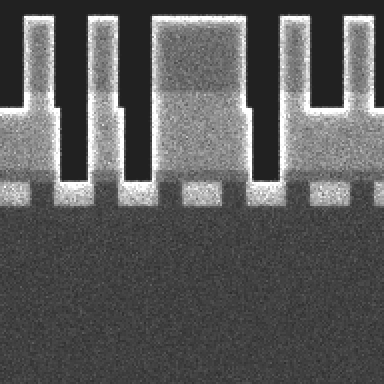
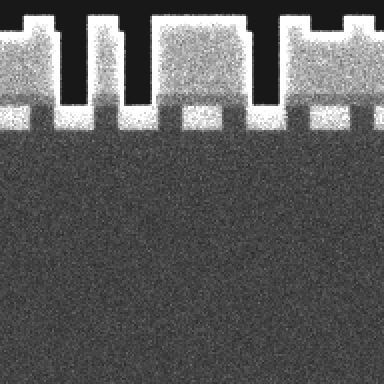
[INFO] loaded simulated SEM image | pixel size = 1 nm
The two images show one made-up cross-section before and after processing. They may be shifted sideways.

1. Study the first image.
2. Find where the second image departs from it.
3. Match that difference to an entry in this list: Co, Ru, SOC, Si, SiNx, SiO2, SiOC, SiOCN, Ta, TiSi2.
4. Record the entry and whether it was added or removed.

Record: SOC / removed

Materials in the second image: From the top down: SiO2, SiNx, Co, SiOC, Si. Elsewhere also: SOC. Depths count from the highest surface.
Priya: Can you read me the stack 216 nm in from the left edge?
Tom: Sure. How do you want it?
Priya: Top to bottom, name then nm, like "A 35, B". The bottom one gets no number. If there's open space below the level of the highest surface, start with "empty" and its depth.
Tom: SiO2 78, SiNx 12, Co 24, SiOC 12, Si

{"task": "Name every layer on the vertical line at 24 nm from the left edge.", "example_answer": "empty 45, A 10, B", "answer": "SiO2 78, SiNx 12, Co 24, SiOC 12, Si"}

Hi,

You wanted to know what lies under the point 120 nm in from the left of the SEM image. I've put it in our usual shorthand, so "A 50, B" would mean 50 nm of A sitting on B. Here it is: empty 16, SiO2 62, SiNx 12, Co 24, SiOC 12, Si